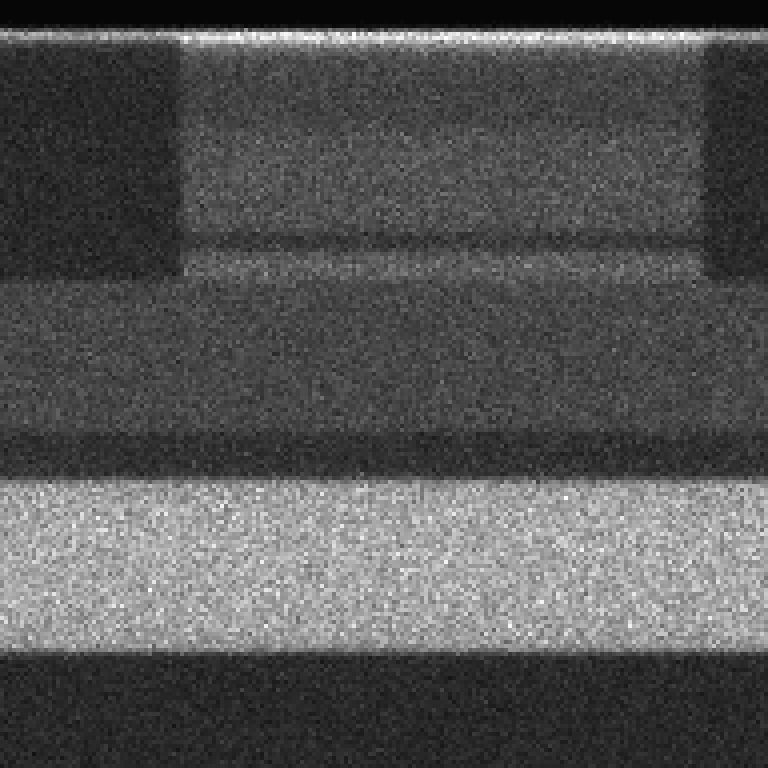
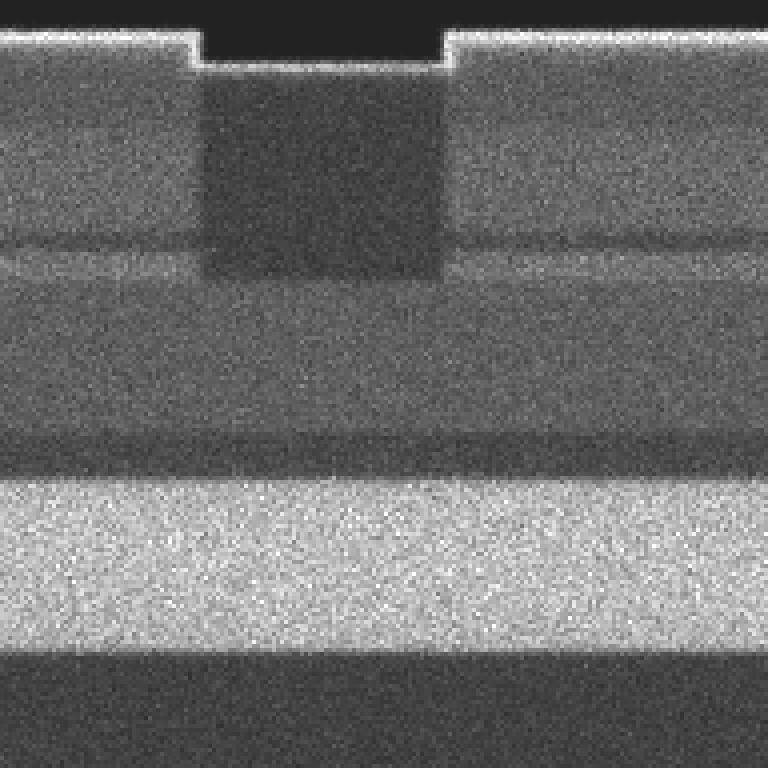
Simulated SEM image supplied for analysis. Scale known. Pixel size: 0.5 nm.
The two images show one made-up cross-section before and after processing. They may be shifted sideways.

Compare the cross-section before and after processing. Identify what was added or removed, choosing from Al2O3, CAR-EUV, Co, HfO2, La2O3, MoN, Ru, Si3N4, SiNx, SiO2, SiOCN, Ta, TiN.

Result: SiNx removed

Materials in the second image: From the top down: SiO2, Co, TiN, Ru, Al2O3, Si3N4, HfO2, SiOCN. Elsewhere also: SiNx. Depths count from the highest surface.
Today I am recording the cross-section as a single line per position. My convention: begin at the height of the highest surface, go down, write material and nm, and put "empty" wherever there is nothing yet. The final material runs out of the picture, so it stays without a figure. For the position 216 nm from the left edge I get empty 16, SiNx 108, Al2O3 76, Si3N4 24, HfO2 86, SiOCN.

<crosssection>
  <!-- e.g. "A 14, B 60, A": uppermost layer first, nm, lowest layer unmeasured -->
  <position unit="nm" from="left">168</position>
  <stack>empty 16, SiNx 108, Al2O3 76, Si3N4 24, HfO2 86, SiOCN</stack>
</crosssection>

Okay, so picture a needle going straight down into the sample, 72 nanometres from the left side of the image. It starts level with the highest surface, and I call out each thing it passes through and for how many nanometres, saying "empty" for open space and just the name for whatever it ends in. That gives SiO2 48, Co 52, TiN 10, Ru 14, Al2O3 76, Si3N4 24, HfO2 86, SiOCN